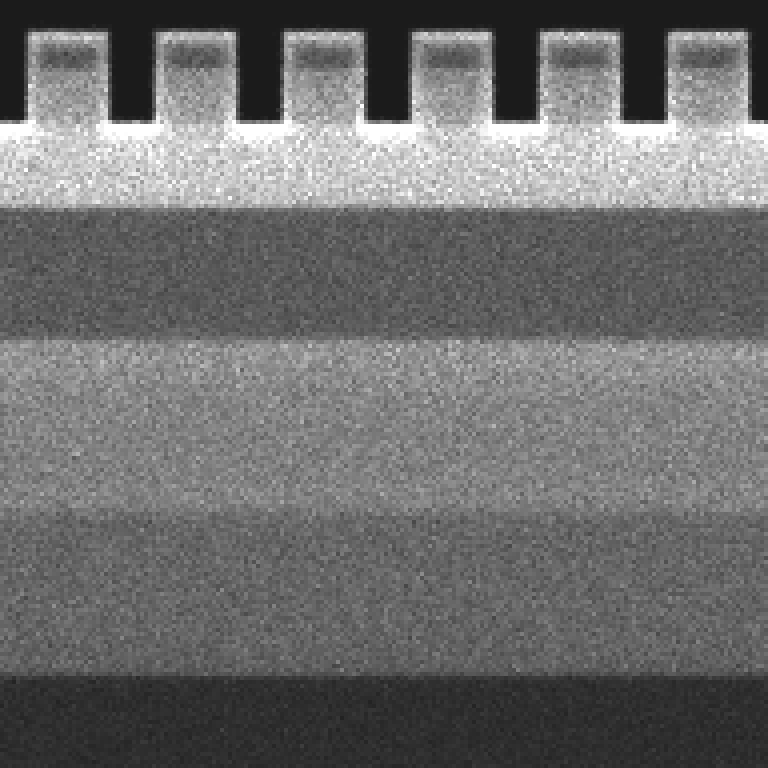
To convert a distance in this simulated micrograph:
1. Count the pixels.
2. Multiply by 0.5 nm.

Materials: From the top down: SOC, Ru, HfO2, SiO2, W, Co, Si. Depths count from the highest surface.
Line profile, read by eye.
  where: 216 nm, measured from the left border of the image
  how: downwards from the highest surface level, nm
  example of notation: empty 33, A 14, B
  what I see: SOC 18, Ru 28, HfO2 42, SiO2 66, W 86, Co 82, Si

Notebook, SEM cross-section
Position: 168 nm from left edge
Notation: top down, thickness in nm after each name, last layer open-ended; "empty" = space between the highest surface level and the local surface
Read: SOC 18, Ru 28, HfO2 42, SiO2 66, W 86, Co 82, Si